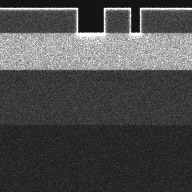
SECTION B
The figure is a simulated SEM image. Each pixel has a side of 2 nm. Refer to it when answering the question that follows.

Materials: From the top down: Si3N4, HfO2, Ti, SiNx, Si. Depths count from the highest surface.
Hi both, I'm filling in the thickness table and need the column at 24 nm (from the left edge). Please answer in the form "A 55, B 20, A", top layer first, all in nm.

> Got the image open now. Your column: Si3N4 50, HfO2 74, Ti 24, SiNx 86, Si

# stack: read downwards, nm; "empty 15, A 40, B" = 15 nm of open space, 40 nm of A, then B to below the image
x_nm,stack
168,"empty 50, HfO2 74, Ti 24, SiNx 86, Si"